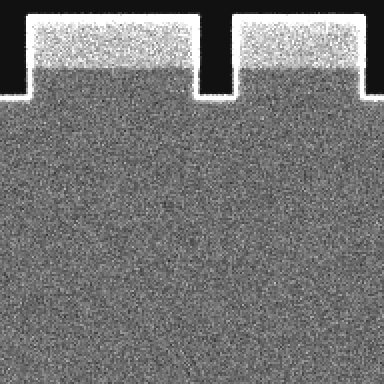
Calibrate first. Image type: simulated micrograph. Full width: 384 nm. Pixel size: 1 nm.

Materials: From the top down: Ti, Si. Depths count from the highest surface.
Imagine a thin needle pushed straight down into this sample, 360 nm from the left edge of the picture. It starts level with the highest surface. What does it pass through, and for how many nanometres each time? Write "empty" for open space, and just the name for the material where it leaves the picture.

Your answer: Ti 52, Si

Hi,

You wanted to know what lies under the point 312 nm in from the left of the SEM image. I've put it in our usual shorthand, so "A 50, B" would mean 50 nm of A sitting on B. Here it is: Ti 52, Si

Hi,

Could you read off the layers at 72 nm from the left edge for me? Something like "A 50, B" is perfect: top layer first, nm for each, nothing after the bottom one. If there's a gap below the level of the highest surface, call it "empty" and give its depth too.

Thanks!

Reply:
Ti 52, Si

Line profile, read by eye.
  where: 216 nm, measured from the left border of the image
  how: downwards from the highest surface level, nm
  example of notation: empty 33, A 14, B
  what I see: empty 80, Si